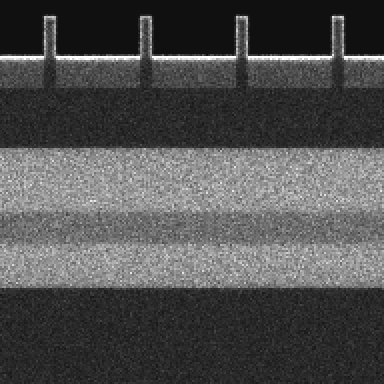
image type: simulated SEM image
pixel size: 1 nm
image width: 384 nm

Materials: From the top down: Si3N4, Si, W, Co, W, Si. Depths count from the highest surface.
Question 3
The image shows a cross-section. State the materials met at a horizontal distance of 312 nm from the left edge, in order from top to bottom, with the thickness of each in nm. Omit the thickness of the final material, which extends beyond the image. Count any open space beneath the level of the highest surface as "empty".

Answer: empty 40, Si3N4 32, Si 60, W 64, Co 32, W 44, Si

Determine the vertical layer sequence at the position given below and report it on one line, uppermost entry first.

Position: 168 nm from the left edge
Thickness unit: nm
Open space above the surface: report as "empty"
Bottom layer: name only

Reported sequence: empty 40, Si3N4 32, Si 60, W 64, Co 32, W 44, Si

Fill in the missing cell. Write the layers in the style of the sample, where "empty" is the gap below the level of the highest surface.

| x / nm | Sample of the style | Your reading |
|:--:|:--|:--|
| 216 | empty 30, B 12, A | empty 40, Si3N4 32, Si 60, W 64, Co 32, W 44, Si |